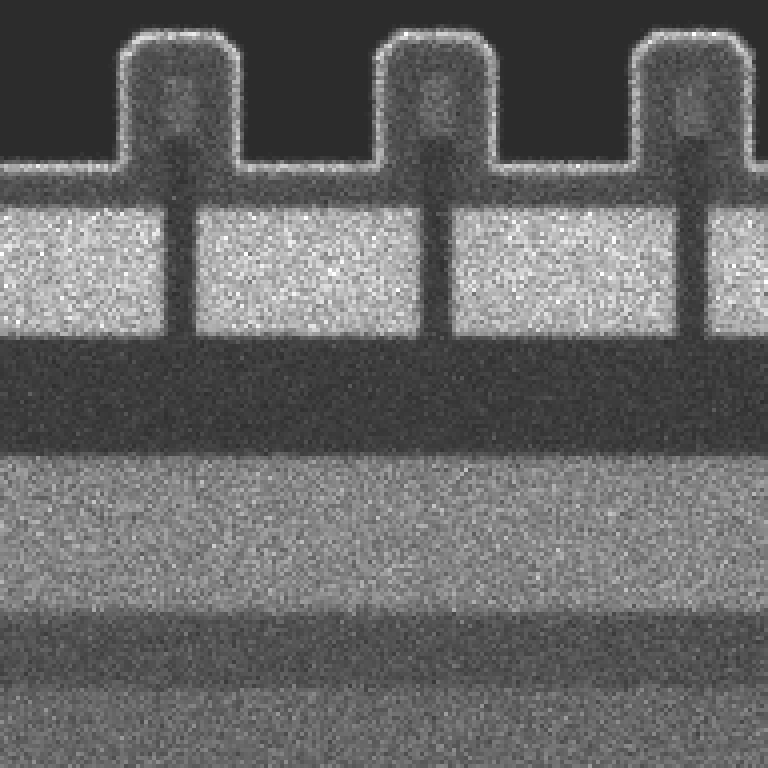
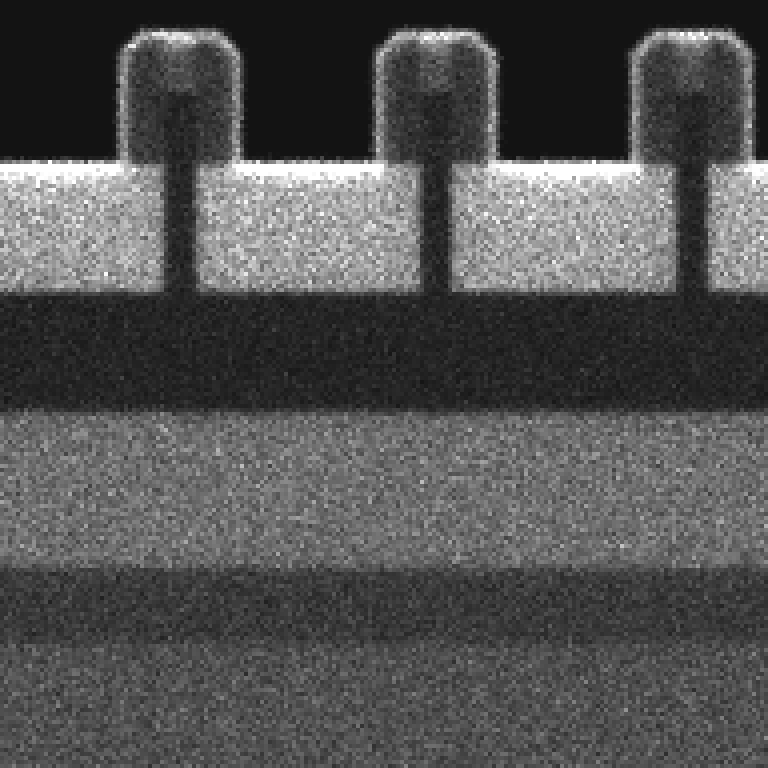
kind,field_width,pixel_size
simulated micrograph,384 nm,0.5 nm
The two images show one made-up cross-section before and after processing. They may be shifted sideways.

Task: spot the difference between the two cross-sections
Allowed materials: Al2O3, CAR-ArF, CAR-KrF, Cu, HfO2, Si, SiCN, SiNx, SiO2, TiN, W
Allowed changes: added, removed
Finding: removed SiNx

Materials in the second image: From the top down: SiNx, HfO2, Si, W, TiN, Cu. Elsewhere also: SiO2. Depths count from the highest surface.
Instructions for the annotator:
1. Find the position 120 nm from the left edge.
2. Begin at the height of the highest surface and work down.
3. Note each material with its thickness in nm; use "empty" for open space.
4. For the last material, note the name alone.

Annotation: empty 66, HfO2 64, Si 60, W 78, TiN 38, Cu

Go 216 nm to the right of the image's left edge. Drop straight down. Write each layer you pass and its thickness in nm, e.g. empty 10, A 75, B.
SiO2 30, Si 160, W 78, TiN 38, Cu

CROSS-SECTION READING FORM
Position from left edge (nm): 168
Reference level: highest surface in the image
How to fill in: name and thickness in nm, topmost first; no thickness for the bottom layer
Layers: empty 66, HfO2 64, Si 60, W 78, TiN 38, Cu